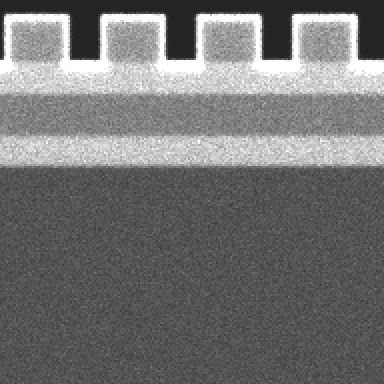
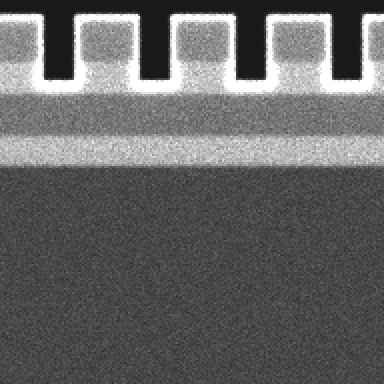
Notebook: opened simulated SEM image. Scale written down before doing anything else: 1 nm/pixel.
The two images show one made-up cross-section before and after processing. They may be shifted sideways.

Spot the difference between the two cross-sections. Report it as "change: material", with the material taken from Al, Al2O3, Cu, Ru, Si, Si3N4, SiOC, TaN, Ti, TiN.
removed: Al2O3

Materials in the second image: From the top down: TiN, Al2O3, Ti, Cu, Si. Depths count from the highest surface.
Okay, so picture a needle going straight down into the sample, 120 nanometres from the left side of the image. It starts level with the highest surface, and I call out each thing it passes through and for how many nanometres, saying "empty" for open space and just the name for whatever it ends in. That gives TiN 46, Al2O3 32, Ti 42, Cu 30, Si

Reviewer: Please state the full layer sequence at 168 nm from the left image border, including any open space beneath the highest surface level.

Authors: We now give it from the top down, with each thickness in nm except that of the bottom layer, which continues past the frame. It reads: empty 66, Al2O3 12, Ti 42, Cu 30, Si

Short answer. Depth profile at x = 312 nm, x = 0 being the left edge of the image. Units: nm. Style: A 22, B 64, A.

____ TiN 46, Al2O3 32, Ti 42, Cu 30, Si